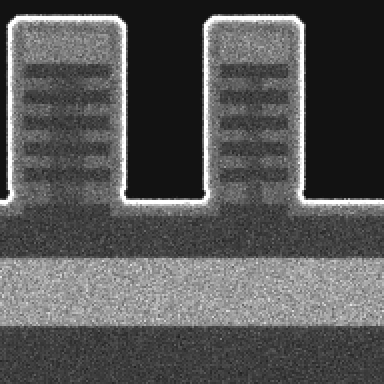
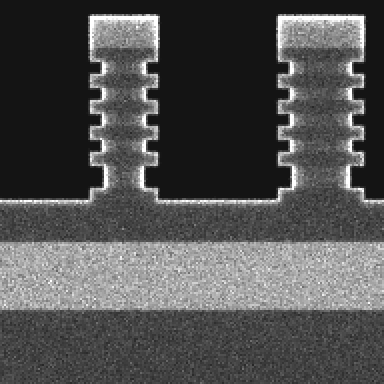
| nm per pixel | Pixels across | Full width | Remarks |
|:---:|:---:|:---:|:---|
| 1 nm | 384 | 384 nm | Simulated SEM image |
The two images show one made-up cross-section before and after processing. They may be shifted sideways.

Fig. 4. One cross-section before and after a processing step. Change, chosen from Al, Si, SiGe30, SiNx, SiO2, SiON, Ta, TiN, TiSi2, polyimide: SiNx removed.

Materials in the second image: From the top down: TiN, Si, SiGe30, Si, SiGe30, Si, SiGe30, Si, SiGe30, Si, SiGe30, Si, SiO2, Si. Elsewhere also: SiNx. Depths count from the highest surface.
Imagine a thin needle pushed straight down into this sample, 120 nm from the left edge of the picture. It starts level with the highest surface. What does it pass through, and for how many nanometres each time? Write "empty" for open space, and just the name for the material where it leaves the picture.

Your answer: TiN 32, Si 14, SiGe30 12, Si 14, SiGe30 12, Si 14, SiGe30 12, Si 14, SiGe30 12, Si 14, SiGe30 22, Si 54, SiO2 68, Si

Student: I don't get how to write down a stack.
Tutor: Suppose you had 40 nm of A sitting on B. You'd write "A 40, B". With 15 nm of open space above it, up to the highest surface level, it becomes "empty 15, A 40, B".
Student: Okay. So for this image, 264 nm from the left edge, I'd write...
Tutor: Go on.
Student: empty 184, Si 42, SiO2 68, Si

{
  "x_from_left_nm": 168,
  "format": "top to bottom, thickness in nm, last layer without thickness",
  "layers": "empty 184, Si 42, SiO2 68, Si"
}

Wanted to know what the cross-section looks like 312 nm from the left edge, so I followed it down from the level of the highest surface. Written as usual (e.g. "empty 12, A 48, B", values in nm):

TiN 32, Si 14, SiGe30 12, Si 14, SiGe30 12, Si 14, SiGe30 12, Si 14, SiGe30 12, Si 14, SiGe30 22, Si 54, SiO2 68, Si